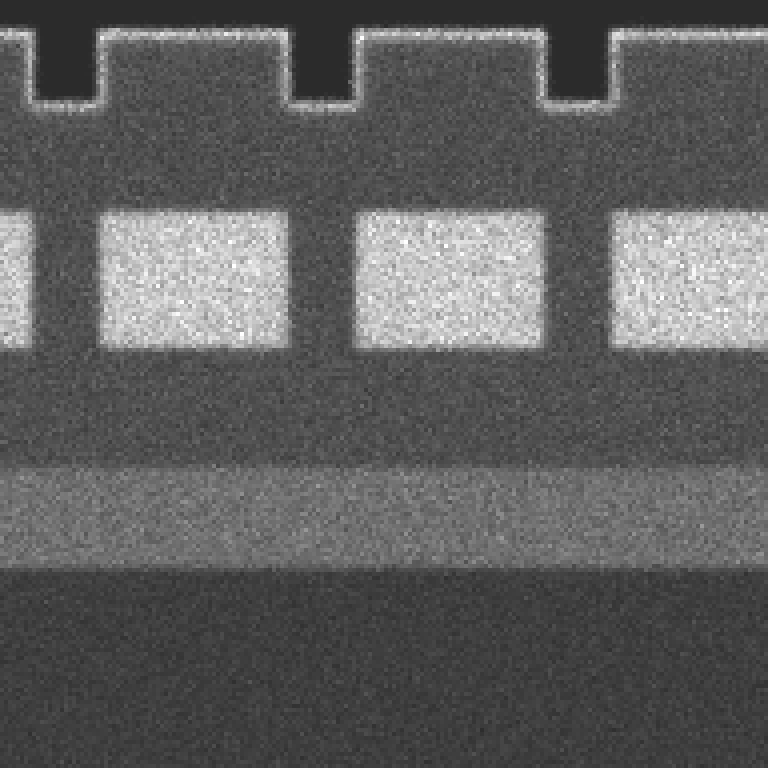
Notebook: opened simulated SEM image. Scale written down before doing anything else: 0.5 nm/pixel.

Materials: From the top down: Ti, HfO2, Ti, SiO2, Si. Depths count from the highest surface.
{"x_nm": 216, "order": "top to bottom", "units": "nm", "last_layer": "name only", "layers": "Ti 90, HfO2 68, Ti 60, SiO2 50, Si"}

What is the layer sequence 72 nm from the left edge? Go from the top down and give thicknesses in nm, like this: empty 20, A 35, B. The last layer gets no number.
Ti 90, HfO2 68, Ti 60, SiO2 50, Si